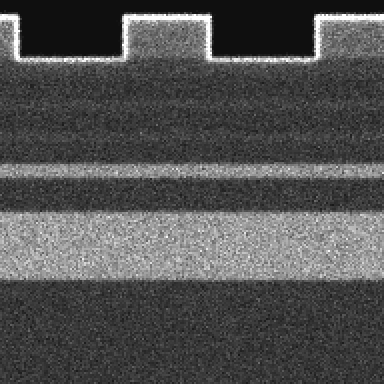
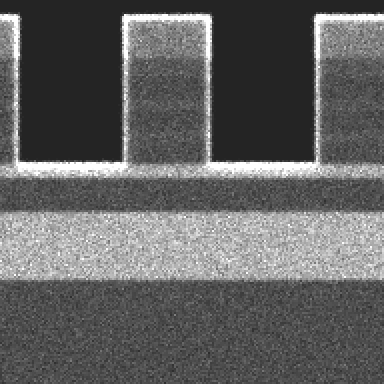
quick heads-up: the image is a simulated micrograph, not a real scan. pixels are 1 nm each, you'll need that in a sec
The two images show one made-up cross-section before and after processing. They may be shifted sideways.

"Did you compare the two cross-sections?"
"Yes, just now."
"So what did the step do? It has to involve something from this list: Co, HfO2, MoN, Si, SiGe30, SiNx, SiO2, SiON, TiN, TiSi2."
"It removed Si and SiGe30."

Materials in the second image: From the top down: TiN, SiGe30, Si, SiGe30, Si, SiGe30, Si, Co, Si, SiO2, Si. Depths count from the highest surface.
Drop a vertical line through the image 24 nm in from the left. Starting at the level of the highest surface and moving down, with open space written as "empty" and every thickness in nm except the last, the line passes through empty 148, Co 14, Si 34, SiO2 68, Si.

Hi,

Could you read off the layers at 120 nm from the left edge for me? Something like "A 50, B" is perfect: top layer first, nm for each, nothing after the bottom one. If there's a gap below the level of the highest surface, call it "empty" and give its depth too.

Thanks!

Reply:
empty 148, Co 14, Si 34, SiO2 68, Si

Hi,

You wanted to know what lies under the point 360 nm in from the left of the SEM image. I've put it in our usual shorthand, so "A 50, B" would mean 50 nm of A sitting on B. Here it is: TiN 42, SiGe30 20, Si 22, SiGe30 10, Si 22, SiGe30 10, Si 22, Co 14, Si 34, SiO2 68, Si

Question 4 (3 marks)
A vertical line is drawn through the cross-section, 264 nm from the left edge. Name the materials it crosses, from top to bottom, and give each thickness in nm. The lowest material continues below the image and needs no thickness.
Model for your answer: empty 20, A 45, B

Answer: empty 148, Co 14, Si 34, SiO2 68, Si